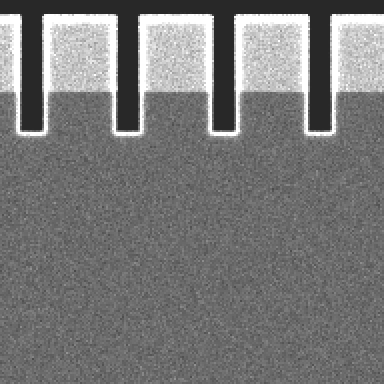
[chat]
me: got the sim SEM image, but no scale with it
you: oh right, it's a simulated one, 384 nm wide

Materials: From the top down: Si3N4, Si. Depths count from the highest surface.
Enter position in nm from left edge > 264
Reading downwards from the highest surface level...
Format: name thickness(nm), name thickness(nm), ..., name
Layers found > Si3N4 76, Si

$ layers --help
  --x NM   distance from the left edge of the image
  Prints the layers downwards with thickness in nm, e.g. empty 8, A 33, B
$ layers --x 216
empty 116, Si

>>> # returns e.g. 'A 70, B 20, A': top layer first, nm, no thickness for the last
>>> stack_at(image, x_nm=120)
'empty 116, Si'